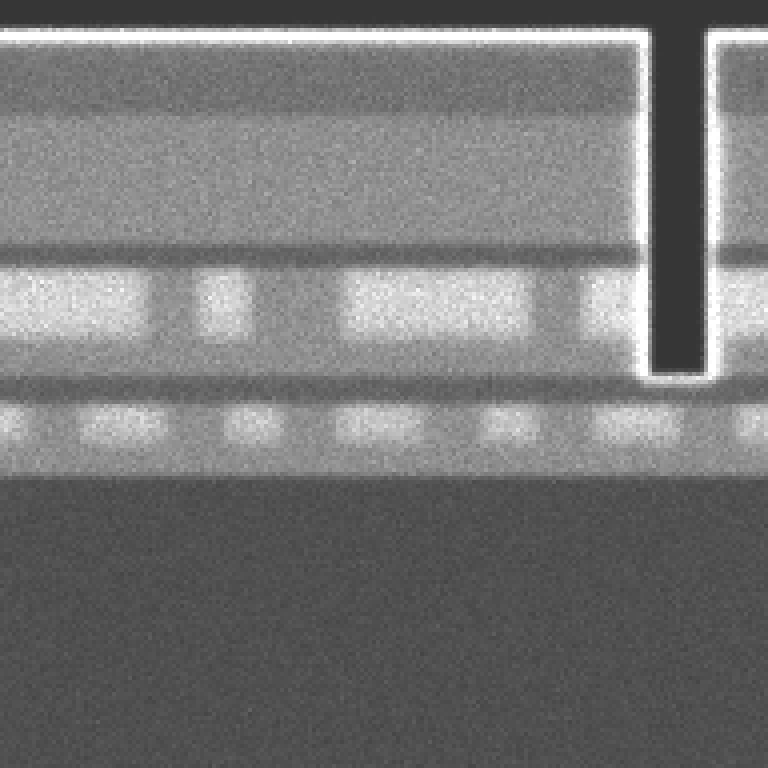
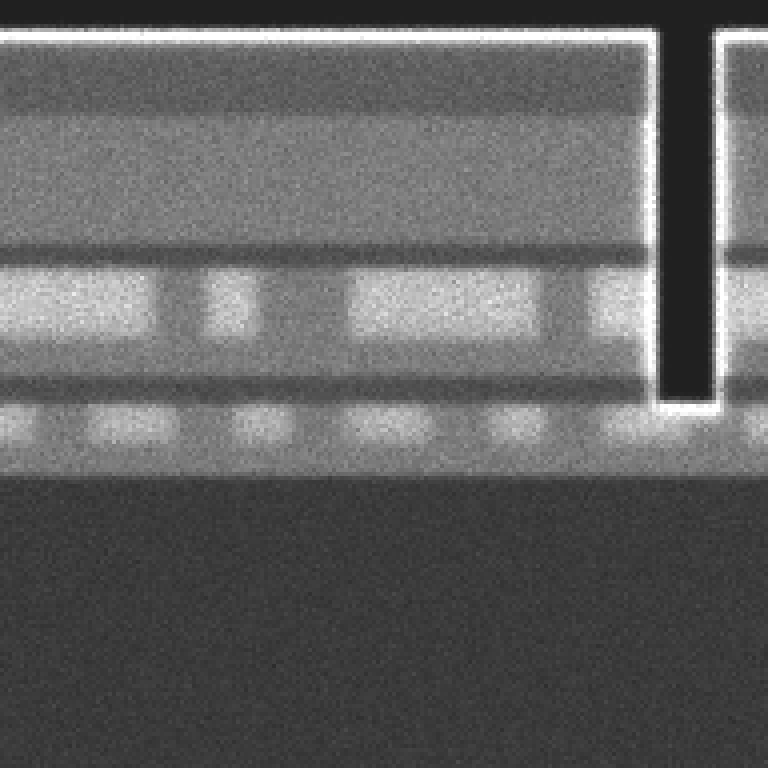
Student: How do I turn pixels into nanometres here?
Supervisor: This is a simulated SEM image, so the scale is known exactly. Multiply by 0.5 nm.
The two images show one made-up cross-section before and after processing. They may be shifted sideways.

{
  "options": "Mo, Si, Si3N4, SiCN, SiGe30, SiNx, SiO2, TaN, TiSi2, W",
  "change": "removed",
  "material": "SiCN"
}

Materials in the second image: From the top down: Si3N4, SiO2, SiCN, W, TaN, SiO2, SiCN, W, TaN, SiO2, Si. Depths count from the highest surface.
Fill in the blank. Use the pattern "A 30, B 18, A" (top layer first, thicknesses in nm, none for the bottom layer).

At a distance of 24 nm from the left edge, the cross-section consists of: Si3N4 42, SiO2 64, SiCN 12, W 30, TaN 6, SiO2 18, SiCN 14, SiO2 36, Si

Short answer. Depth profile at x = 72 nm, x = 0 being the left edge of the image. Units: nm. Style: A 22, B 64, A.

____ Si3N4 42, SiO2 64, SiCN 12, TaN 36, SiO2 18, SiCN 14, W 14, TaN 6, SiO2 16, Si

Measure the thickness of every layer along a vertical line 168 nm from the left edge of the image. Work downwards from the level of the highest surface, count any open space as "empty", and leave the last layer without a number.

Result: Si3N4 42, SiO2 64, SiCN 12, SiO2 54, SiCN 14, SiO2 36, Si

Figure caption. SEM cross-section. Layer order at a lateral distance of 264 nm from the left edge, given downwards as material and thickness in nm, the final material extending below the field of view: Si3N4 42, SiO2 64, SiCN 12, TaN 36, SiO2 18, SiCN 14, W 14, TaN 6, SiO2 16, Si